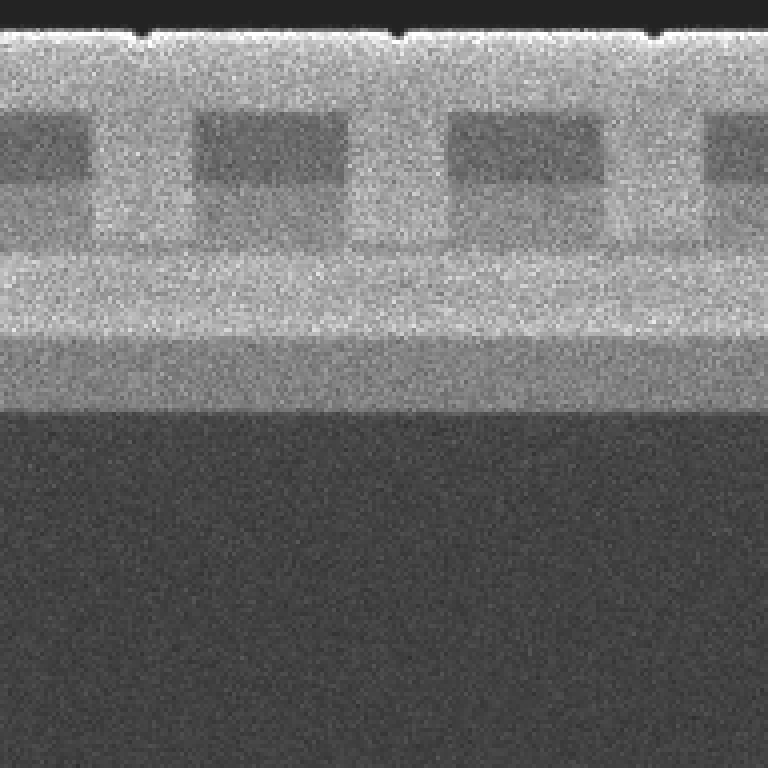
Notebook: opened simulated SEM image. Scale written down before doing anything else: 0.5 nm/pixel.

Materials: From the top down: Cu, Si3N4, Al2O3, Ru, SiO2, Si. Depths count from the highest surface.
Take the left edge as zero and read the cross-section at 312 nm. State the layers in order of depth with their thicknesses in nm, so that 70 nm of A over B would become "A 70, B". Cu 104, Al2O3 8, Ru 40, SiO2 38, Si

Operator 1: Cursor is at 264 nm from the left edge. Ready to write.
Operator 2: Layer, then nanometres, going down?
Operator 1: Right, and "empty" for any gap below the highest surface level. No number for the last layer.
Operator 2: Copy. Cu 40, Si3N4 36, Al2O3 36, Ru 40, SiO2 38, Si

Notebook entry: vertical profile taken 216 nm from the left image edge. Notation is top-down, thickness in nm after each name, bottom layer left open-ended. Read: Cu 104, Al2O3 8, Ru 40, SiO2 38, Si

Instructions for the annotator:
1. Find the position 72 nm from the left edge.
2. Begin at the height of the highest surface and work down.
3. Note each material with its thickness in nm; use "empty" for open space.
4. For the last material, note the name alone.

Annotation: empty 4, Cu 100, Al2O3 8, Ru 40, SiO2 38, Si